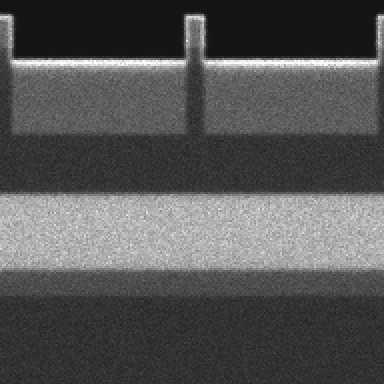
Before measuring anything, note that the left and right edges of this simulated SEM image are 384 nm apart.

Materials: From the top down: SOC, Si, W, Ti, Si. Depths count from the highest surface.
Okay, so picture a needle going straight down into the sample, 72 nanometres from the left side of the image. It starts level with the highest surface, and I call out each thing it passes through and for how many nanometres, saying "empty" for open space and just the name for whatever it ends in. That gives empty 44, SOC 74, Si 60, W 76, Ti 26, Si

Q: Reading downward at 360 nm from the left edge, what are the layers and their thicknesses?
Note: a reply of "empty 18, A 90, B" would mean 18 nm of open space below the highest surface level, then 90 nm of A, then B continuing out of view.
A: empty 44, SOC 74, Si 60, W 76, Ti 26, Si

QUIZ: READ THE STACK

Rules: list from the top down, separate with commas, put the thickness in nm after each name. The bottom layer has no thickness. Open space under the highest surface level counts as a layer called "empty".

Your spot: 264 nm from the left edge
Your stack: empty 44, SOC 74, Si 60, W 76, Ti 26, Si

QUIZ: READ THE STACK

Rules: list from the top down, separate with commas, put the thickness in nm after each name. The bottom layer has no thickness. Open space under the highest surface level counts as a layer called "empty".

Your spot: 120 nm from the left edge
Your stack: empty 44, SOC 74, Si 60, W 76, Ti 26, Si